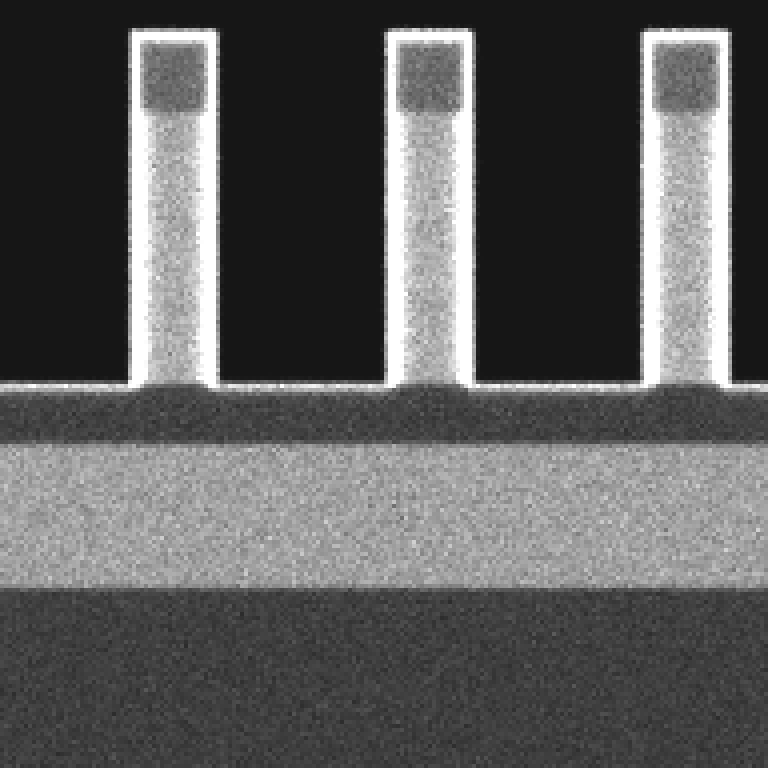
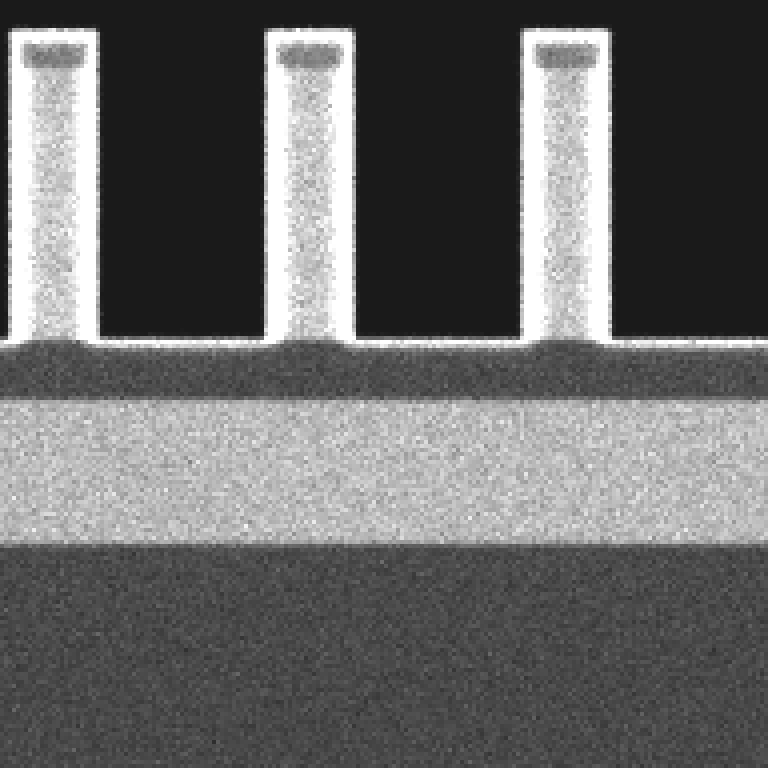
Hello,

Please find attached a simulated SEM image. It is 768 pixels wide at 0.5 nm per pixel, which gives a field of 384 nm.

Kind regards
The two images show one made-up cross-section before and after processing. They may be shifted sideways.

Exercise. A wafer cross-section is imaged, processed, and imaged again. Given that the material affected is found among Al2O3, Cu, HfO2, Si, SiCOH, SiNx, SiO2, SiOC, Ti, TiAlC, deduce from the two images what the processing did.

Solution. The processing removed SiNx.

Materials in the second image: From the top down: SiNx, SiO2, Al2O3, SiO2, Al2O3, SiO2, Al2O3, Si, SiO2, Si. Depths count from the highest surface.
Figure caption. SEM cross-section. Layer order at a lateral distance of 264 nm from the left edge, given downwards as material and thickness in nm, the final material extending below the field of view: SiNx 18, SiO2 20, Al2O3 32, SiO2 10, Al2O3 32, SiO2 10, Al2O3 32, Si 30, SiO2 72, Si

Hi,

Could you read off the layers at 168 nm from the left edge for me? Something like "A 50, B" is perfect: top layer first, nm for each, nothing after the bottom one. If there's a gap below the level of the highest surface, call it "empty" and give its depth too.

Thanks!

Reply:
SiNx 18, SiO2 20, Al2O3 32, SiO2 10, Al2O3 32, SiO2 10, Al2O3 32, Si 30, SiO2 72, Si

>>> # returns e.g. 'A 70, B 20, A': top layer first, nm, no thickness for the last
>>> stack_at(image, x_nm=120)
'empty 154, Si 30, SiO2 72, Si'